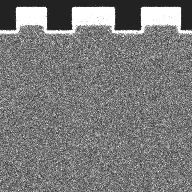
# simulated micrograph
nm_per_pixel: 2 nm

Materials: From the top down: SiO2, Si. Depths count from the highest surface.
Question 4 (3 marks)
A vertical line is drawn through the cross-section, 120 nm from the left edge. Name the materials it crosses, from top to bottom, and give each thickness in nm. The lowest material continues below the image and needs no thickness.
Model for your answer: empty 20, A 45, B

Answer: empty 46, Si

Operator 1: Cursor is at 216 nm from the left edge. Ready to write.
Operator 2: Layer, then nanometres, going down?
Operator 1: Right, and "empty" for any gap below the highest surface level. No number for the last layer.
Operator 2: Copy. SiO2 34, Si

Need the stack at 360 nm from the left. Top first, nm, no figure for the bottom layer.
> empty 46, Si